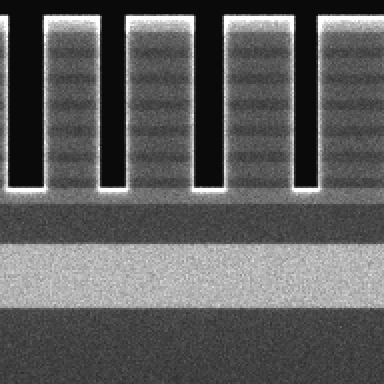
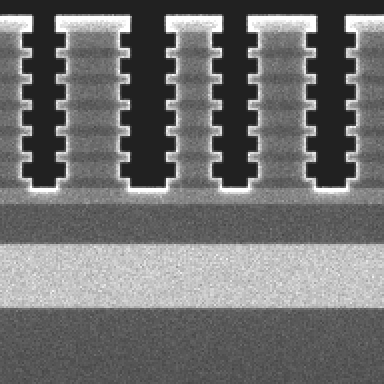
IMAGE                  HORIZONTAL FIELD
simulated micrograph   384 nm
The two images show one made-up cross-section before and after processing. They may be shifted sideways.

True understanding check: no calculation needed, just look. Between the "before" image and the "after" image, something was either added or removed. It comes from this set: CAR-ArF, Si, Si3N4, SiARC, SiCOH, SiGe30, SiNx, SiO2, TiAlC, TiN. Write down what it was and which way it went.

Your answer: SiGe30 (removed)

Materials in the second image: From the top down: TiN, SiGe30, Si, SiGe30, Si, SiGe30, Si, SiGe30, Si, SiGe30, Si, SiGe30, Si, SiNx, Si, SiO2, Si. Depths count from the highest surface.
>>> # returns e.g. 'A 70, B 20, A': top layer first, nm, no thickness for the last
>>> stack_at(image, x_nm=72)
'TiN 16, SiGe30 16, Si 10, SiGe30 16, Si 10, SiGe30 16, Si 10, SiGe30 16, Si 10, SiGe30 16, Si 10, SiGe30 16, Si 10, SiNx 16, Si 40, SiO2 64, Si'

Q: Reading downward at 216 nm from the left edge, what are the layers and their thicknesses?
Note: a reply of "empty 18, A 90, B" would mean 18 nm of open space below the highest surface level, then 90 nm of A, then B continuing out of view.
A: TiN 16, empty 16, Si 10, empty 16, Si 10, empty 16, Si 10, empty 16, Si 10, empty 16, Si 10, empty 16, Si 10, SiNx 16, Si 40, SiO2 64, Si